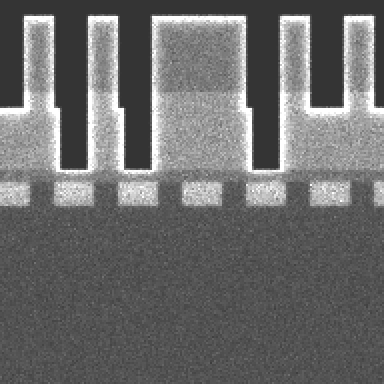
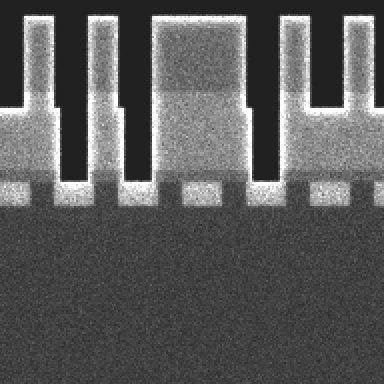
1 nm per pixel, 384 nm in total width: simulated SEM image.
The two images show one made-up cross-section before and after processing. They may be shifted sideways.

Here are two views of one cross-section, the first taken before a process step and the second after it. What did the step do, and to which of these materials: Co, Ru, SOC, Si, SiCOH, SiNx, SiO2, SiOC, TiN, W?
It removed SiNx.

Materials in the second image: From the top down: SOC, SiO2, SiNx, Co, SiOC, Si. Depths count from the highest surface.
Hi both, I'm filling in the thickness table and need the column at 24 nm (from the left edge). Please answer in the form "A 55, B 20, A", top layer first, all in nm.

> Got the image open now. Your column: SOC 76, SiO2 78, SiNx 12, Co 24, SiOC 12, Si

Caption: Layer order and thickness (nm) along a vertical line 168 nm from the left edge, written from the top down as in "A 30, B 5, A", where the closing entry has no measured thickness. SOC 76, SiO2 78, SiNx 12, SiOC 36, Si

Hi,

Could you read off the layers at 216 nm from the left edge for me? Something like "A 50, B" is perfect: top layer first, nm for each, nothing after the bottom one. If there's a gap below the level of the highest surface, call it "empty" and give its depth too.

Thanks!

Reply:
SOC 76, SiO2 78, SiNx 12, Co 24, SiOC 12, Si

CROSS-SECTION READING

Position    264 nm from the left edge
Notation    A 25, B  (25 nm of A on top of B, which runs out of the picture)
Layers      empty 166, Co 24, SiOC 12, Si